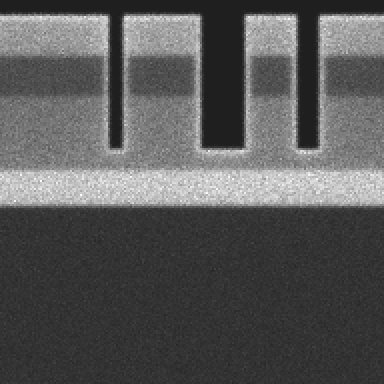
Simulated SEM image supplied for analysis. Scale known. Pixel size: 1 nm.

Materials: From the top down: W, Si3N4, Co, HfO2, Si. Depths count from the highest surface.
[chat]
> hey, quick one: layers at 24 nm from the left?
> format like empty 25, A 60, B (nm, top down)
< W 40, Si3N4 40, Co 74, HfO2 36, Si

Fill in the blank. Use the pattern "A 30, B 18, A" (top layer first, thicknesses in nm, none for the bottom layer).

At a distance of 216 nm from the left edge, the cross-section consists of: empty 134, Co 20, HfO2 36, Si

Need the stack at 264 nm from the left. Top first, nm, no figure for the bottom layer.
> W 40, Si3N4 40, Co 74, HfO2 36, Si